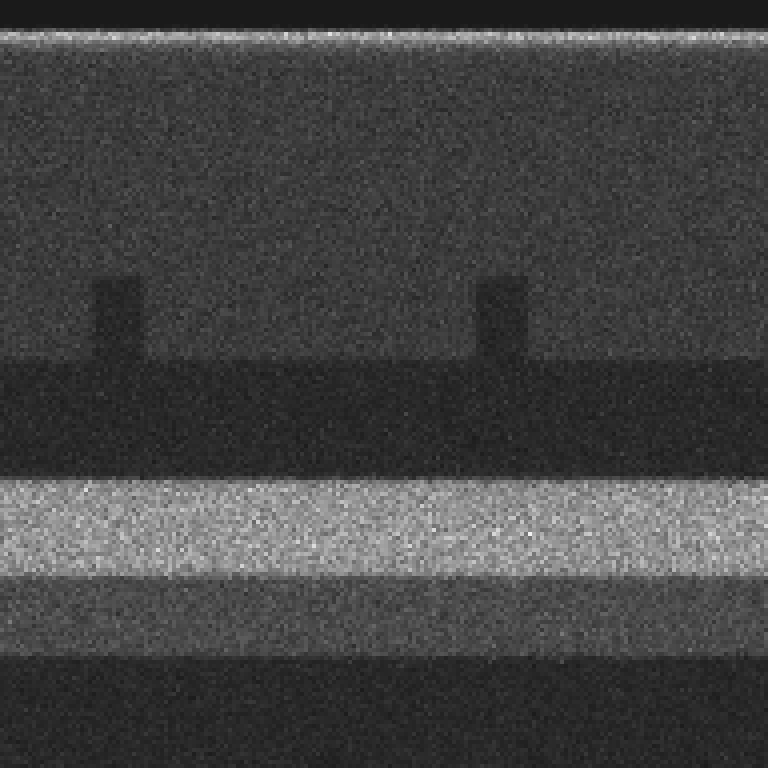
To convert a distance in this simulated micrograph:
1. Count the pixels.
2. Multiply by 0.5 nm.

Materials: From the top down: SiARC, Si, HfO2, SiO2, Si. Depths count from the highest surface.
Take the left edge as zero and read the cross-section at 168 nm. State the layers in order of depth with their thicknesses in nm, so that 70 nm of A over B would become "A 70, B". SiARC 164, Si 60, HfO2 48, SiO2 40, Si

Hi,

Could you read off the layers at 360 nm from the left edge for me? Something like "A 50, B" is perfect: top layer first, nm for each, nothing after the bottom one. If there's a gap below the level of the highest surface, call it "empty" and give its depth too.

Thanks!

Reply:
SiARC 164, Si 60, HfO2 48, SiO2 40, Si